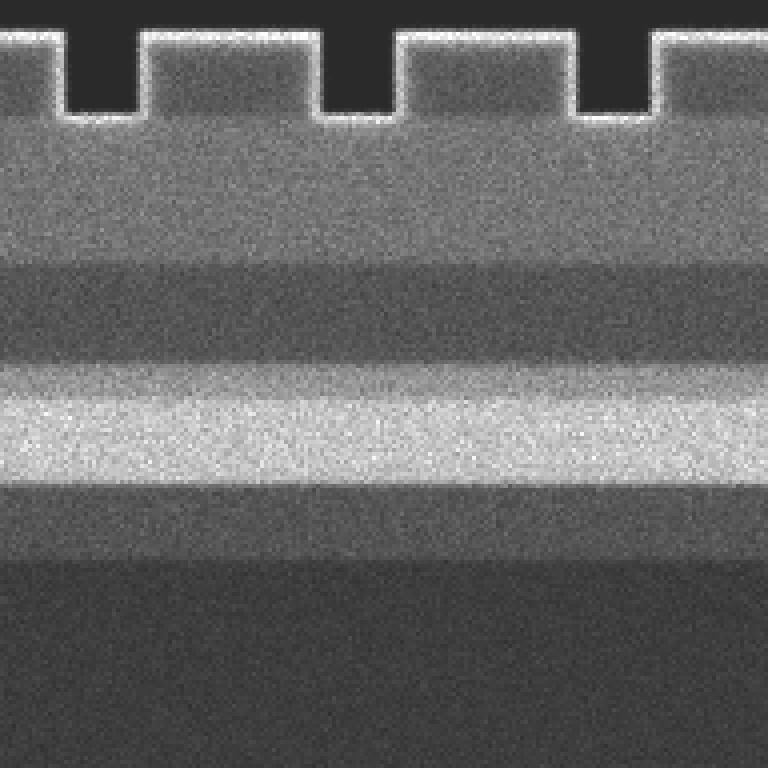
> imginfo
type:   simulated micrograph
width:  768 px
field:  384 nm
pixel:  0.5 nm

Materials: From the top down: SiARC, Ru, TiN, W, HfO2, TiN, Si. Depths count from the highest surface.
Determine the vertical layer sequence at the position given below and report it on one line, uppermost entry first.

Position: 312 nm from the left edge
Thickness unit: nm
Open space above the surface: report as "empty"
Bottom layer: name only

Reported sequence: empty 42, Ru 74, TiN 50, W 18, HfO2 42, TiN 38, Si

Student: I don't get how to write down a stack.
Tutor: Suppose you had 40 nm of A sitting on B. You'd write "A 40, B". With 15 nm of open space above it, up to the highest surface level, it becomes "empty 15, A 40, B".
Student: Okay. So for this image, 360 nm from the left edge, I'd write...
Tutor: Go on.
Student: SiARC 42, Ru 74, TiN 50, W 18, HfO2 42, TiN 38, Si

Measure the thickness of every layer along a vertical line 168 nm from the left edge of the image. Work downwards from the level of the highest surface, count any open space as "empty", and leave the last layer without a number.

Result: empty 42, Ru 74, TiN 50, W 18, HfO2 42, TiN 38, Si